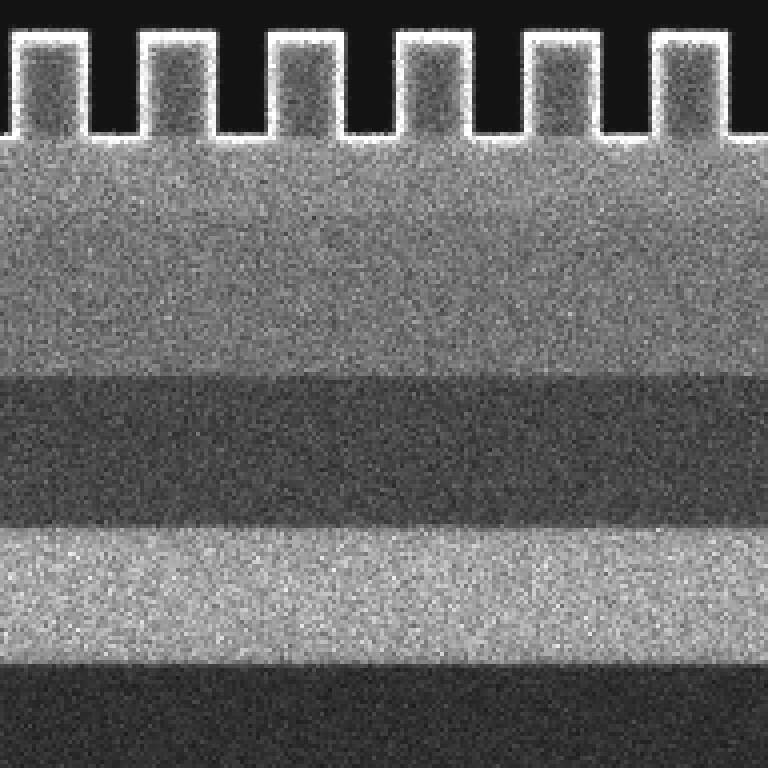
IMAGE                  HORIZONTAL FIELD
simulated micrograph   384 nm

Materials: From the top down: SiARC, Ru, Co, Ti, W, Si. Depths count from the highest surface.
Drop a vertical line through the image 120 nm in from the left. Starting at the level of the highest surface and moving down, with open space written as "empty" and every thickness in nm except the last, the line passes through empty 52, Ru 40, Co 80, Ti 76, W 68, Si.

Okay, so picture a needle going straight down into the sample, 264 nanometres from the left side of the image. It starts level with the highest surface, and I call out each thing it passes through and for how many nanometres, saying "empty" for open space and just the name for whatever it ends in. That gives SiARC 52, Ru 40, Co 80, Ti 76, W 68, Si